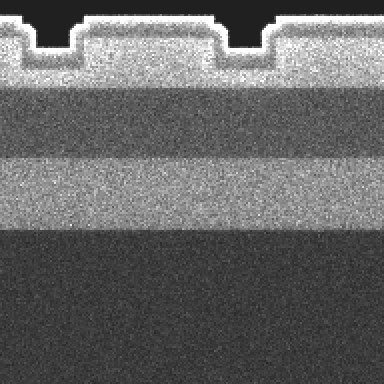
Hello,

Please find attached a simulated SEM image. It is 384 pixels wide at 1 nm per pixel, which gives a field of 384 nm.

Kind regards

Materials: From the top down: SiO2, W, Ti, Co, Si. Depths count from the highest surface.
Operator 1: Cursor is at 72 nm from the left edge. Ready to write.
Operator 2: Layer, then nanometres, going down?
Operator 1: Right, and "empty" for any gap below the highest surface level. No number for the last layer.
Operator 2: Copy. empty 12, SiO2 42, W 18, Ti 70, Co 72, Si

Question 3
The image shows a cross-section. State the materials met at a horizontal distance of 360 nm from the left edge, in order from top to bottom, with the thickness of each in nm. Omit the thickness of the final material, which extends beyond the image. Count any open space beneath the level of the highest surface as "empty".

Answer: SiO2 22, W 50, Ti 70, Co 72, Si